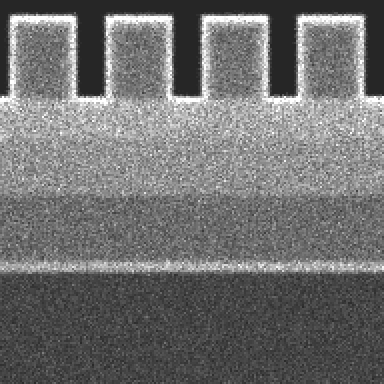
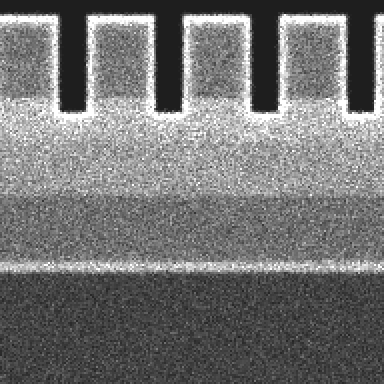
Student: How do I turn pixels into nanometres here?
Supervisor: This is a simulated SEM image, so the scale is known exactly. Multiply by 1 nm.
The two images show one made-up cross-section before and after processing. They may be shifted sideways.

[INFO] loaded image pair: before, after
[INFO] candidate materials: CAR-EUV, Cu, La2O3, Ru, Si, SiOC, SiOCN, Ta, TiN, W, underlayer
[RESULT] removed Ru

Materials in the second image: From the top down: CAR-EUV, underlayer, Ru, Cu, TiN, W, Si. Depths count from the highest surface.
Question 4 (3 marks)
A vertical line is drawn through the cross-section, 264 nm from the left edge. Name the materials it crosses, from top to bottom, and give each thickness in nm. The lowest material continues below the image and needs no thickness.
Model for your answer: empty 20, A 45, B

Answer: empty 98, Ru 26, Cu 56, TiN 66, W 10, Si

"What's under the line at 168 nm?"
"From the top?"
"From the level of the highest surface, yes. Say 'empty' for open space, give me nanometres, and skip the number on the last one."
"empty 98, Ru 26, Cu 56, TiN 66, W 10, Si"